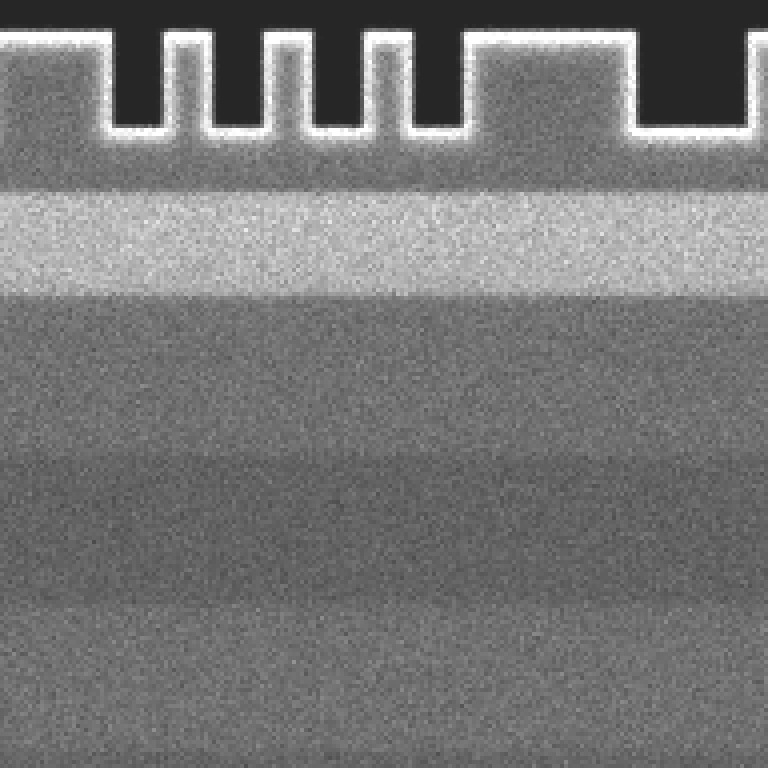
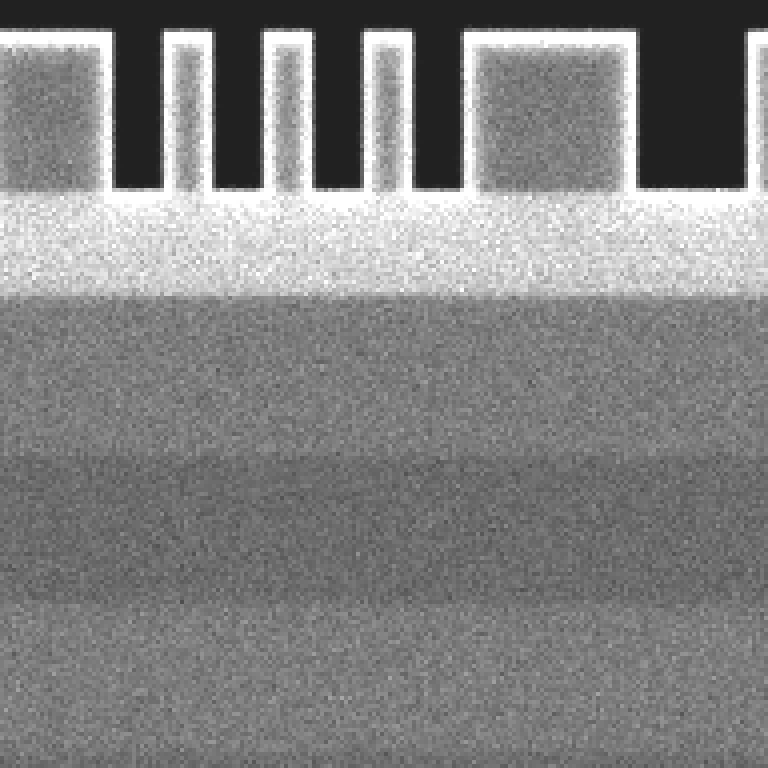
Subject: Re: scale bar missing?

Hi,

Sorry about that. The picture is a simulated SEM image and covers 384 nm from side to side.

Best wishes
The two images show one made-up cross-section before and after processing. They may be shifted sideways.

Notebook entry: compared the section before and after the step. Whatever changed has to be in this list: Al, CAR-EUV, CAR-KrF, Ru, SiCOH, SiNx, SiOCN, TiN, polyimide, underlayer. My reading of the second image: underlayer removed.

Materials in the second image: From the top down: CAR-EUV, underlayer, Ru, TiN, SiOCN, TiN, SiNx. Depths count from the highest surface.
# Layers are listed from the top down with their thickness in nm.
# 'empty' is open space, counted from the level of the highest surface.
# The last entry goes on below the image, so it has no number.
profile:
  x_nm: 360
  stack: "empty 80, Ru 52, TiN 80, SiOCN 74, TiN 74, SiNx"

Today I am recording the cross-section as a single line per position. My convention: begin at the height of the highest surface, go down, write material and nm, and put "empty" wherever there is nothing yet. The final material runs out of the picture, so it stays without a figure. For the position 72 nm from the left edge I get empty 80, Ru 52, TiN 80, SiOCN 74, TiN 74, SiNx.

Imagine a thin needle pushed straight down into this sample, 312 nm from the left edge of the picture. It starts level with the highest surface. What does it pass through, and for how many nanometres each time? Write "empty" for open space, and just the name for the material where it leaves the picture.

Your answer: CAR-EUV 48, underlayer 32, Ru 52, TiN 80, SiOCN 74, TiN 74, SiNx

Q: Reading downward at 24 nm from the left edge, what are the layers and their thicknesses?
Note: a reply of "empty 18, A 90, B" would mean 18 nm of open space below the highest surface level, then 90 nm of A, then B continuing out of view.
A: CAR-EUV 48, underlayer 32, Ru 52, TiN 80, SiOCN 74, TiN 74, SiNx